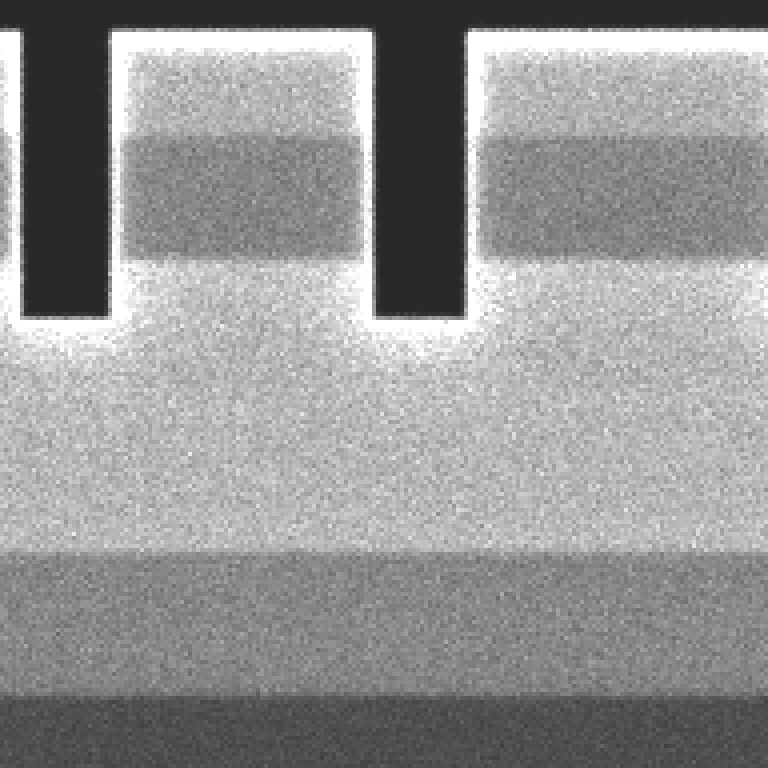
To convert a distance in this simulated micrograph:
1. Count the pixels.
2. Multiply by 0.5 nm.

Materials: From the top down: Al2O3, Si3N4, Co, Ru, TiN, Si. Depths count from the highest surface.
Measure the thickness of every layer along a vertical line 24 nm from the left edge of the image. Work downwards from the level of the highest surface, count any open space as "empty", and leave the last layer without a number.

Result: empty 144, Co 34, Ru 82, TiN 72, Si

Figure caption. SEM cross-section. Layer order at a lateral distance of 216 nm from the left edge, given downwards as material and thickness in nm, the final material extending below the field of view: empty 144, Co 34, Ru 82, TiN 72, Si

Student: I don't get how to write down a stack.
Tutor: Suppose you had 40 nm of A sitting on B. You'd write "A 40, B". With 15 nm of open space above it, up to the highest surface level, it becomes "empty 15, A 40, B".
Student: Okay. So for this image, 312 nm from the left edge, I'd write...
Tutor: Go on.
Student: Al2O3 52, Si3N4 62, Co 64, Ru 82, TiN 72, Si